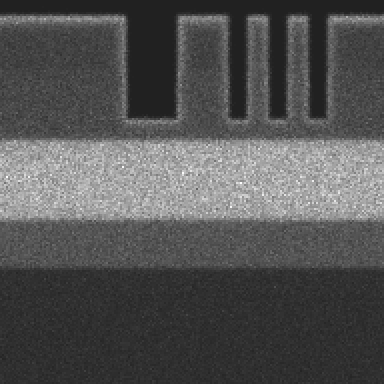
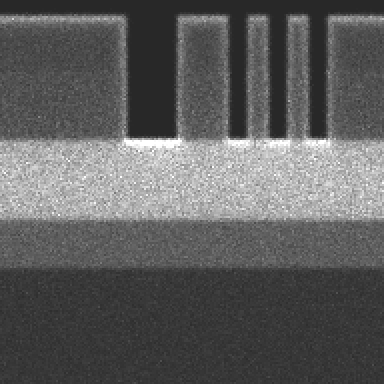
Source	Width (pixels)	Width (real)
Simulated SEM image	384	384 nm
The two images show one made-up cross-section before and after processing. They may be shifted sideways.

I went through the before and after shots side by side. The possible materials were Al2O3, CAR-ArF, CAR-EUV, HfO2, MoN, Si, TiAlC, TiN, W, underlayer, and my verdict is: removed, TiN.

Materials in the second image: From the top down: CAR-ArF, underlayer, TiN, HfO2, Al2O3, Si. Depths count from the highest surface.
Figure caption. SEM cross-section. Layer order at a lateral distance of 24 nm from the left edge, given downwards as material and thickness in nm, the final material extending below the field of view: CAR-ArF 32, underlayer 22, TiN 70, HfO2 80, Al2O3 48, Si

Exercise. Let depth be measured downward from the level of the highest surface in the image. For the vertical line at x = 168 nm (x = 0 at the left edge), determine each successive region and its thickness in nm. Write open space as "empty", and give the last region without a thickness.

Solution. empty 124, HfO2 80, Al2O3 48, Si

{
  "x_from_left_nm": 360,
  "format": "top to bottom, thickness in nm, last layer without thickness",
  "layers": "CAR-ArF 32, underlayer 22, TiN 70, HfO2 80, Al2O3 48, Si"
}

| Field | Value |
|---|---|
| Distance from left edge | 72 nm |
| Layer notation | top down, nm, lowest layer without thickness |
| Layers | CAR-ArF 32, underlayer 22, TiN 70, HfO2 80, Al2O3 48, Si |